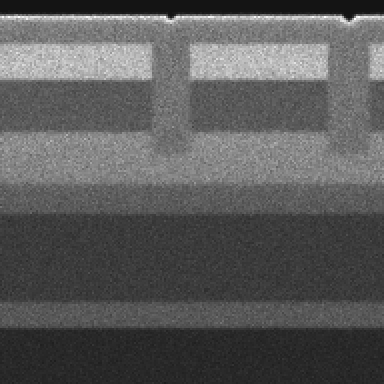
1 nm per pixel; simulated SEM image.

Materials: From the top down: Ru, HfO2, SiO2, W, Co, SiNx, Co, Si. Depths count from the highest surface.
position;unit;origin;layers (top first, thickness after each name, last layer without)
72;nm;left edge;Ru 28, HfO2 36, SiO2 52, W 52, Co 30, SiNx 88, Co 26, Si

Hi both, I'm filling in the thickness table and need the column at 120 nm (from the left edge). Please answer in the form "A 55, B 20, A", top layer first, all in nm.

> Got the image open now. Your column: Ru 28, HfO2 36, SiO2 52, W 52, Co 30, SiNx 88, Co 26, Si